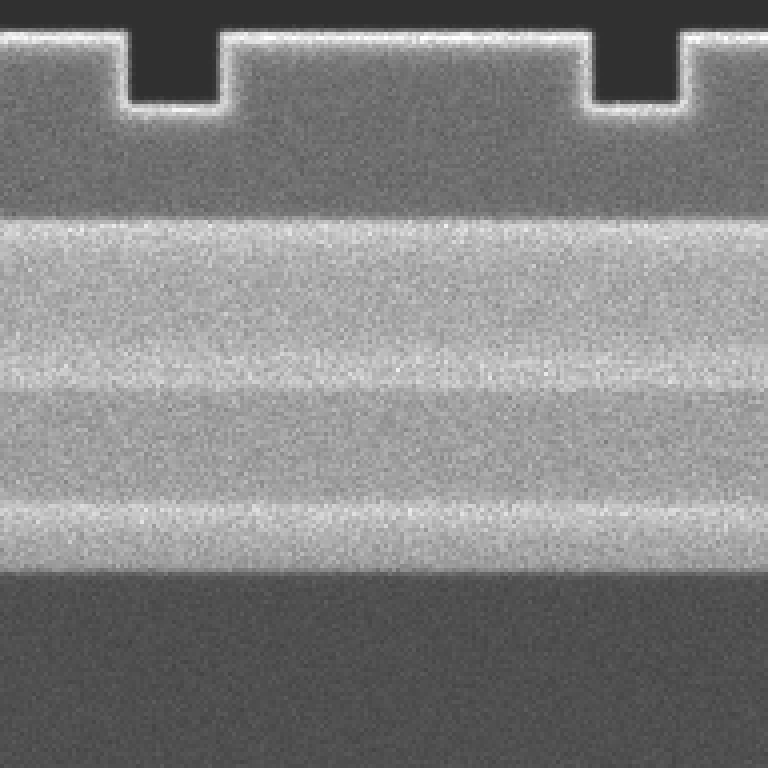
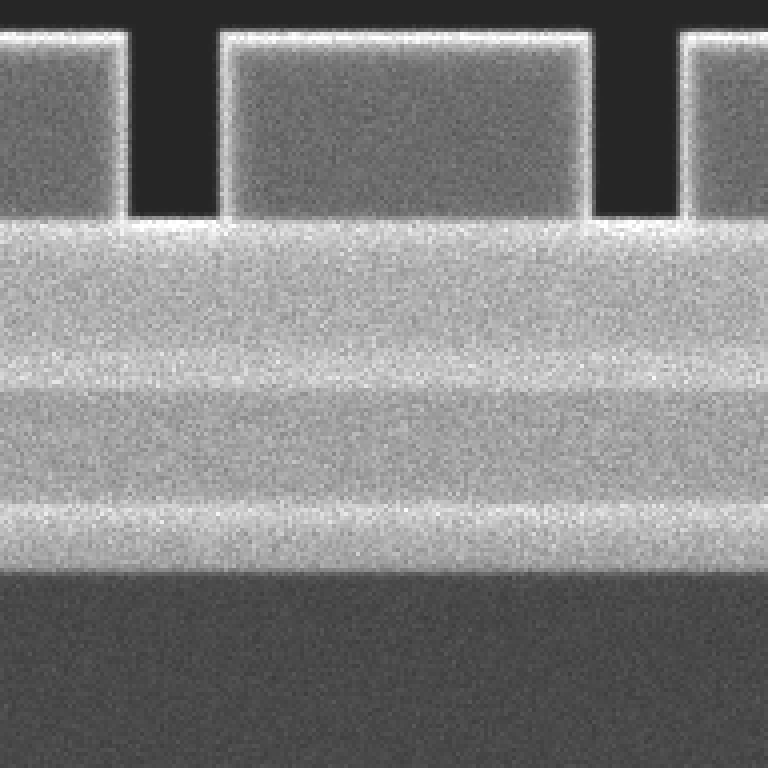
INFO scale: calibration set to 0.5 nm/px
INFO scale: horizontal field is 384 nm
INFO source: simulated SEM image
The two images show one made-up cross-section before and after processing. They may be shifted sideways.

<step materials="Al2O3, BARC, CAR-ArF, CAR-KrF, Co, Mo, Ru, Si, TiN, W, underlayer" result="removed underlayer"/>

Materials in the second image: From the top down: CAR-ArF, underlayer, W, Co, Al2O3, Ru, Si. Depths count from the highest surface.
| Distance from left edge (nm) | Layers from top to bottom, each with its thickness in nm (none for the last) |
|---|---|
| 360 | CAR-ArF 36, underlayer 58, W 72, Co 12, Al2O3 58, Ru 34, Si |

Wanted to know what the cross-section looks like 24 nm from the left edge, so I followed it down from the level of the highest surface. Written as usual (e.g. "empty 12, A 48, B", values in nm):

CAR-ArF 36, underlayer 58, W 72, Co 12, Al2O3 58, Ru 34, Si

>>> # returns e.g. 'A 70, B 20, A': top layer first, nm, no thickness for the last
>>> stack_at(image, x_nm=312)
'empty 94, W 72, Co 12, Al2O3 58, Ru 34, Si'